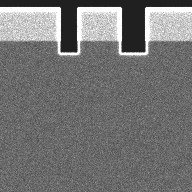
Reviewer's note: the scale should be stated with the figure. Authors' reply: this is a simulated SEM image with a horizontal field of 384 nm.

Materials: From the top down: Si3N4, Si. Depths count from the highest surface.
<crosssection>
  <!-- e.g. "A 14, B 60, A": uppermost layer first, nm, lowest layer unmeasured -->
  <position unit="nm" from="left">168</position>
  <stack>Si3N4 66, Si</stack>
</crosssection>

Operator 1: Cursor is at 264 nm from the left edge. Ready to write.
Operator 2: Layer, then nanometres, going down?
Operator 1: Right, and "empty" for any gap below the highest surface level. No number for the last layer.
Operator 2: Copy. empty 90, Si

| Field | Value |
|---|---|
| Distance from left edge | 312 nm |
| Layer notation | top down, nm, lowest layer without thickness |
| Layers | Si3N4 66, Si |